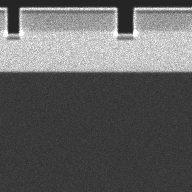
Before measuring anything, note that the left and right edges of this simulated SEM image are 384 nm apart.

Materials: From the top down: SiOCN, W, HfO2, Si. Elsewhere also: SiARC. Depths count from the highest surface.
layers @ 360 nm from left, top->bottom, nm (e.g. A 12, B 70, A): SiOCN 10, W 36, HfO2 82, Si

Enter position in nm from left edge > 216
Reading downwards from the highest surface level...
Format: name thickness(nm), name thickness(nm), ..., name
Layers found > SiOCN 10, W 36, HfO2 82, Si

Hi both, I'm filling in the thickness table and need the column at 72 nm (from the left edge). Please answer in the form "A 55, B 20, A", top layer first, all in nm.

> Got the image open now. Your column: SiOCN 10, W 36, HfO2 82, Si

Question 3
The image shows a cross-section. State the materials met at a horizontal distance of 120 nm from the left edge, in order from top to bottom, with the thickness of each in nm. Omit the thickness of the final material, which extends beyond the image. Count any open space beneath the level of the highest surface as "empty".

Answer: SiOCN 10, W 36, HfO2 82, Si